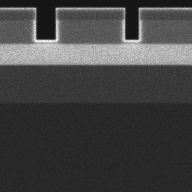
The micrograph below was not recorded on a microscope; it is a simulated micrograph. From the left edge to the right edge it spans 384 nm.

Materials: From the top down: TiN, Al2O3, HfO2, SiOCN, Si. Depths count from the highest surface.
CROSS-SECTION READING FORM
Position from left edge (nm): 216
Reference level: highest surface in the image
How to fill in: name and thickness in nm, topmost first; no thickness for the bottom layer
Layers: TiN 24, Al2O3 48, HfO2 42, SiOCN 76, Si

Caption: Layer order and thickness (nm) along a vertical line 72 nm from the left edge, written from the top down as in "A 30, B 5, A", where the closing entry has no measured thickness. empty 64, Al2O3 8, HfO2 42, SiOCN 76, Si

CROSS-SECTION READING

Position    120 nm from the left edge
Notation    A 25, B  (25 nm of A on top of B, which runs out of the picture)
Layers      TiN 24, Al2O3 48, HfO2 42, SiOCN 76, Si